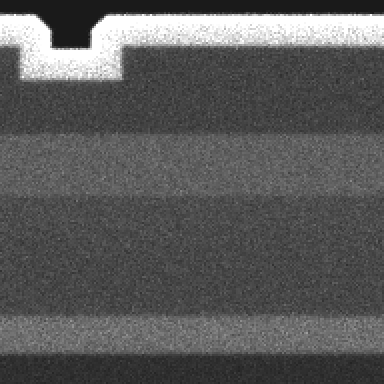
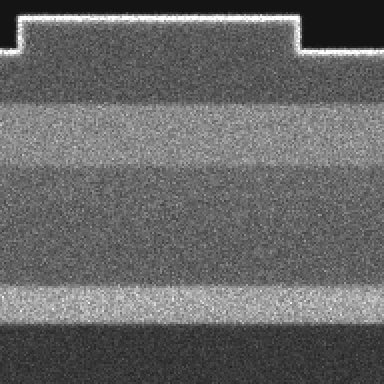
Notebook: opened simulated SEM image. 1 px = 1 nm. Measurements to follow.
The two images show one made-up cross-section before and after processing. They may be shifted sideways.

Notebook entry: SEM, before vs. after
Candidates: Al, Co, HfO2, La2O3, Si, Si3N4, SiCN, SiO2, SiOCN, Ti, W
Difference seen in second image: HfO2 removed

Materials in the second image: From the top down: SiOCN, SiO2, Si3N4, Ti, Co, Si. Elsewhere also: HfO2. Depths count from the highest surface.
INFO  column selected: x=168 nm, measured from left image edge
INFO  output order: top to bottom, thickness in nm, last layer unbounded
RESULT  SiOCN 88, SiO2 62, Si3N4 32, Ti 88, Co 38, Si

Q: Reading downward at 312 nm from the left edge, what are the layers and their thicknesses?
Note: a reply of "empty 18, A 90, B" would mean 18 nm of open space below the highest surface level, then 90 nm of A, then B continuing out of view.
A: empty 34, SiOCN 54, SiO2 62, Si3N4 32, Ti 88, Co 38, Si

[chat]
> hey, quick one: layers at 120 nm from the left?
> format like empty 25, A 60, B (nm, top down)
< SiOCN 88, SiO2 62, Si3N4 32, Ti 88, Co 38, Si